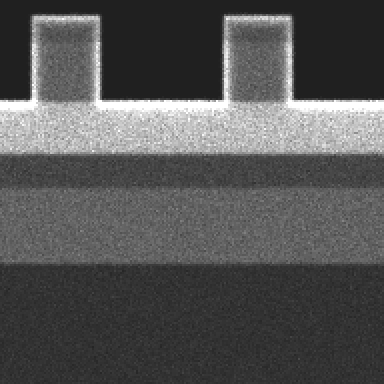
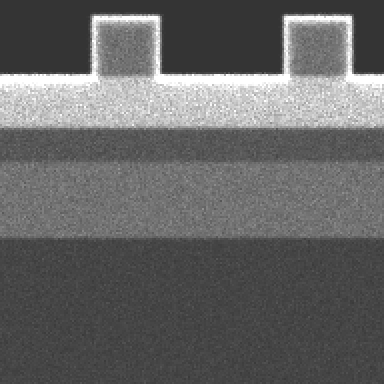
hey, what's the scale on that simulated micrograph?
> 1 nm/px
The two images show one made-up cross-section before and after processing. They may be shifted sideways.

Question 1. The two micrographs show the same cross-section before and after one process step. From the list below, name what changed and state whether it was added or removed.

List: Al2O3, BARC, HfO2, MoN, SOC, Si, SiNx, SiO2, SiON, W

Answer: SOC, removed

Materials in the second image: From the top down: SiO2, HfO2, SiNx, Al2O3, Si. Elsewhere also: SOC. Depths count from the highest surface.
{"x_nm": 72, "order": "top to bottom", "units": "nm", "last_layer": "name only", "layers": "empty 60, HfO2 52, SiNx 34, Al2O3 76, Si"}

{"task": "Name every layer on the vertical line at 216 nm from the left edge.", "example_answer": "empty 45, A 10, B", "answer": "empty 60, HfO2 52, SiNx 34, Al2O3 76, Si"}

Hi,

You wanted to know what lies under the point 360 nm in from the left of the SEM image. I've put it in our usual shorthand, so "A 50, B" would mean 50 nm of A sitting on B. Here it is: empty 60, HfO2 52, SiNx 34, Al2O3 76, Si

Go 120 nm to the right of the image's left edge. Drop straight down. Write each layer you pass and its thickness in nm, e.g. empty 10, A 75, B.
SiO2 60, HfO2 52, SiNx 34, Al2O3 76, Si